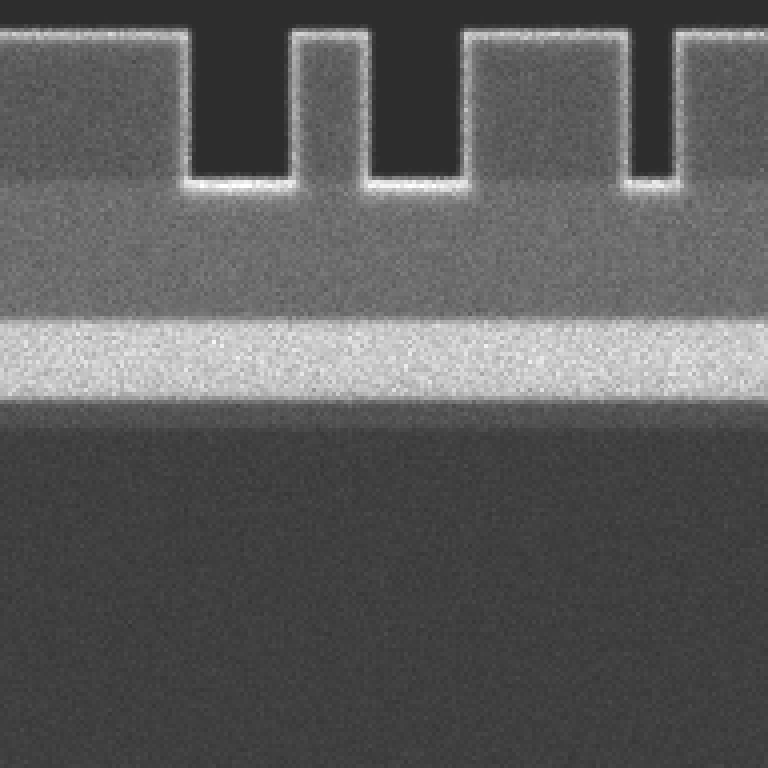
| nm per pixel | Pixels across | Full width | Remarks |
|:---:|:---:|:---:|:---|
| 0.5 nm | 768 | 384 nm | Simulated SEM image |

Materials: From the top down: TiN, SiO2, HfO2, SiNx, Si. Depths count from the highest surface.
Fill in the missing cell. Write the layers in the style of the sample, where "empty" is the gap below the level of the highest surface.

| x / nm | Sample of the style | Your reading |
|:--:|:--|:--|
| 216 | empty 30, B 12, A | empty 74, SiO2 70, HfO2 40, SiNx 14, Si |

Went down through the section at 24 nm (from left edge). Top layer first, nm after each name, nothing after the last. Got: TiN 74, SiO2 70, HfO2 40, SiNx 14, Si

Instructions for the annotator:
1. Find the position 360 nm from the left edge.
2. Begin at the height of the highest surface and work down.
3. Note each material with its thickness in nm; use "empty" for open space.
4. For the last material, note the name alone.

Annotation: TiN 74, SiO2 70, HfO2 40, SiNx 14, Si